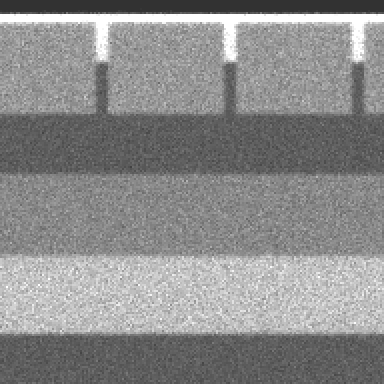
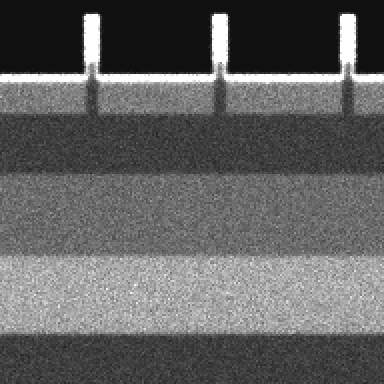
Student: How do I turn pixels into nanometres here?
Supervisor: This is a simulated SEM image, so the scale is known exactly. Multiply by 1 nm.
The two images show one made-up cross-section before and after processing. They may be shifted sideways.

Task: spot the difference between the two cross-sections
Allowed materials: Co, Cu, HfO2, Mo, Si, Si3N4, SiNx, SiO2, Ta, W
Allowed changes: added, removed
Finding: removed Si3N4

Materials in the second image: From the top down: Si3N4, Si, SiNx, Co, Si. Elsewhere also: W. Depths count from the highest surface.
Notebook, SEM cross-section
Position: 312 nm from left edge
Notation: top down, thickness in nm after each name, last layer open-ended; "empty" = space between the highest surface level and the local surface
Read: empty 60, Si3N4 38, Si 60, SiNx 82, Co 78, Si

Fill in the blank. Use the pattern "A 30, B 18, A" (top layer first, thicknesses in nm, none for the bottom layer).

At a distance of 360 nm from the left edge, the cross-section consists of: empty 60, Si3N4 38, Si 60, SiNx 82, Co 78, Si